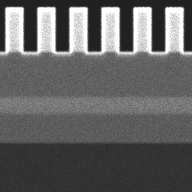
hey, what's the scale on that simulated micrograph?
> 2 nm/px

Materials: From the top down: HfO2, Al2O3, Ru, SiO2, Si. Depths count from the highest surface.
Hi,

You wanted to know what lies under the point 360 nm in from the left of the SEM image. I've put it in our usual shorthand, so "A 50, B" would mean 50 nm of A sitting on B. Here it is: HfO2 88, Al2O3 90, Ru 34, SiO2 58, Si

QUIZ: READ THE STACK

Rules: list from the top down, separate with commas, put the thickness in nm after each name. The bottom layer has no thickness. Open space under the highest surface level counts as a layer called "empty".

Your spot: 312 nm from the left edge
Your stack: empty 88, Al2O3 90, Ru 34, SiO2 58, Si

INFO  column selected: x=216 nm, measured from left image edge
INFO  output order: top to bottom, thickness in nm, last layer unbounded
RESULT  HfO2 88, Al2O3 90, Ru 34, SiO2 58, Si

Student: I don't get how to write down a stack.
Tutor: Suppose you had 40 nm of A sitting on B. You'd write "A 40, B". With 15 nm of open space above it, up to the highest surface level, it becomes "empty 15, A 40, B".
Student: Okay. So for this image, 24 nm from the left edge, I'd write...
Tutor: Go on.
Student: HfO2 88, Al2O3 90, Ru 34, SiO2 58, Si